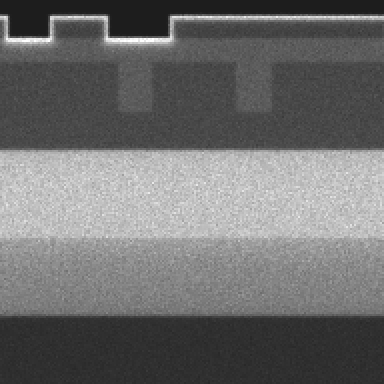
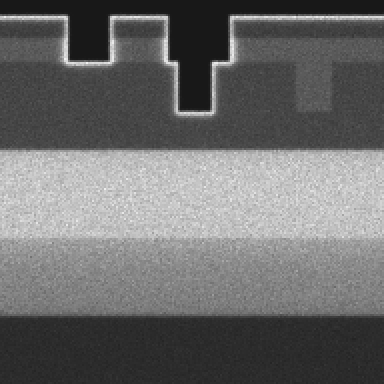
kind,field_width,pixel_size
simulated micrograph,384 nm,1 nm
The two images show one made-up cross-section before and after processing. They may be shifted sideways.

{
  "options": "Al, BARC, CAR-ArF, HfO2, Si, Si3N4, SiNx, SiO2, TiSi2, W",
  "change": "removed",
  "material": "SiO2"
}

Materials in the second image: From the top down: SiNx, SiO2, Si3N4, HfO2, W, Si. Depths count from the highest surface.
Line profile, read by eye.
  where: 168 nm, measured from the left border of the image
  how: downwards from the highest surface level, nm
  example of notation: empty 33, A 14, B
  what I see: empty 46, Si3N4 88, HfO2 88, W 78, Si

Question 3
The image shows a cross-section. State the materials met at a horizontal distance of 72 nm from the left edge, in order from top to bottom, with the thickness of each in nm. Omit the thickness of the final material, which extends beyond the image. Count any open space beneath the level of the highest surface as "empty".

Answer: empty 46, Si3N4 88, HfO2 88, W 78, Si